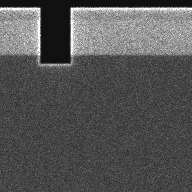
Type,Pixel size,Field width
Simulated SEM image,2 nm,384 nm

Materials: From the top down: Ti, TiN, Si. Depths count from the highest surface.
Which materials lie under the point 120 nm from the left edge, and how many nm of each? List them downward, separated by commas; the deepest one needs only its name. empty 112, Si